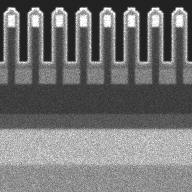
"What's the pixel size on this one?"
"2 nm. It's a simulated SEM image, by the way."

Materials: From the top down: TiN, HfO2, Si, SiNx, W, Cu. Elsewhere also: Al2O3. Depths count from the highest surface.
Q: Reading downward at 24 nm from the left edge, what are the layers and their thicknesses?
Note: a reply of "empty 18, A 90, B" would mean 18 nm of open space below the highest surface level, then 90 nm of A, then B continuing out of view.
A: TiN 14, HfO2 24, Si 174, SiNx 30, W 72, Cu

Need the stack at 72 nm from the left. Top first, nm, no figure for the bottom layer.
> TiN 14, HfO2 24, Si 174, SiNx 30, W 72, Cu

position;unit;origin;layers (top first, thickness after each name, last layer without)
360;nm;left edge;TiN 14, HfO2 24, Si 174, SiNx 30, W 72, Cu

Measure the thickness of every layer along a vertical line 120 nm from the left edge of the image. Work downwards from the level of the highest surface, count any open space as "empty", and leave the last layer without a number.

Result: TiN 14, HfO2 24, Si 174, SiNx 30, W 72, Cu